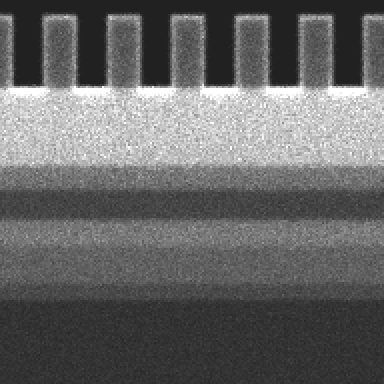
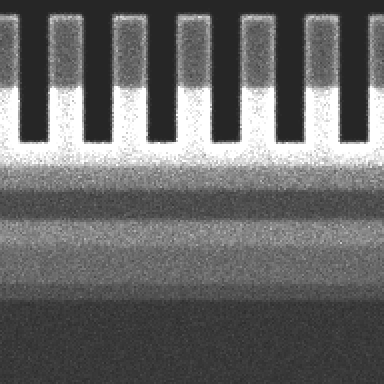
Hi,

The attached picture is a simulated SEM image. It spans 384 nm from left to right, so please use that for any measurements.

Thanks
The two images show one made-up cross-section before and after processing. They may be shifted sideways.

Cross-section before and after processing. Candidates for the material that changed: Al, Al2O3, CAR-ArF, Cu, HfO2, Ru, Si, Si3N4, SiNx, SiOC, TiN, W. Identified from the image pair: HfO2 (removed).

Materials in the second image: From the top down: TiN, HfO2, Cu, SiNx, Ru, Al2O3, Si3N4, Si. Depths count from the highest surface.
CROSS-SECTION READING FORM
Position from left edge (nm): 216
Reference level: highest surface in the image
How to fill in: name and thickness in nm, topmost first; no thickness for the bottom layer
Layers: empty 128, HfO2 22, Cu 24, SiNx 30, Ru 26, Al2O3 38, Si3N4 16, Si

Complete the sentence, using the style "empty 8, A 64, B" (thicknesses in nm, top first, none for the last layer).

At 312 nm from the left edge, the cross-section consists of TiN 72, HfO2 78, Cu 24, SiNx 30, Ru 26, Al2O3 38, Si3N4 16, Si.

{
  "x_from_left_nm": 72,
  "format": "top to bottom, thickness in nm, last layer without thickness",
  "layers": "TiN 72, HfO2 78, Cu 24, SiNx 30, Ru 26, Al2O3 38, Si3N4 16, Si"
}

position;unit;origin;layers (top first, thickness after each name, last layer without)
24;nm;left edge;empty 128, HfO2 22, Cu 24, SiNx 30, Ru 26, Al2O3 38, Si3N4 16, Si